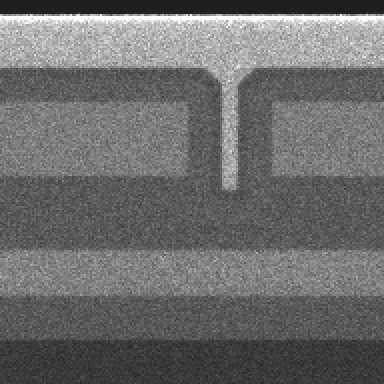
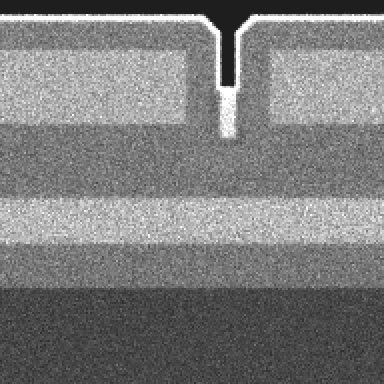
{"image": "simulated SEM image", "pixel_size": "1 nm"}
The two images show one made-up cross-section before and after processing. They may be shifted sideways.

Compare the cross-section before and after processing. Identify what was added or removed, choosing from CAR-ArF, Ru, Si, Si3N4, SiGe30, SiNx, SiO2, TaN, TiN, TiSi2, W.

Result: W removed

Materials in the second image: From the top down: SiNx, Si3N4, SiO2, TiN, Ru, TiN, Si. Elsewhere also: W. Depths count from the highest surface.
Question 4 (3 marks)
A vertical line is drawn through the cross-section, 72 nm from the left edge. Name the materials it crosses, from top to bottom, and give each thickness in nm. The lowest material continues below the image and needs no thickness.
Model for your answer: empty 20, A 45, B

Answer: SiNx 10, Si3N4 24, SiO2 74, TiN 74, Ru 46, TiN 44, Si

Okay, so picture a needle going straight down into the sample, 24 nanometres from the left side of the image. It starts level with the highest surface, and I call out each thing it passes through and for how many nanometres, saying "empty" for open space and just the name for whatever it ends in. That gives SiNx 10, Si3N4 24, SiO2 74, TiN 74, Ru 46, TiN 44, Si